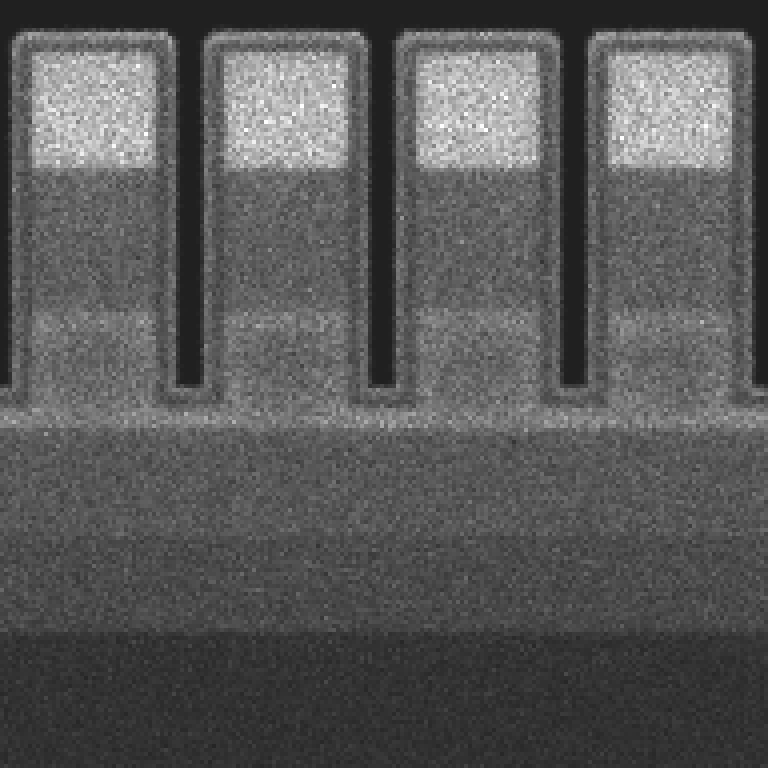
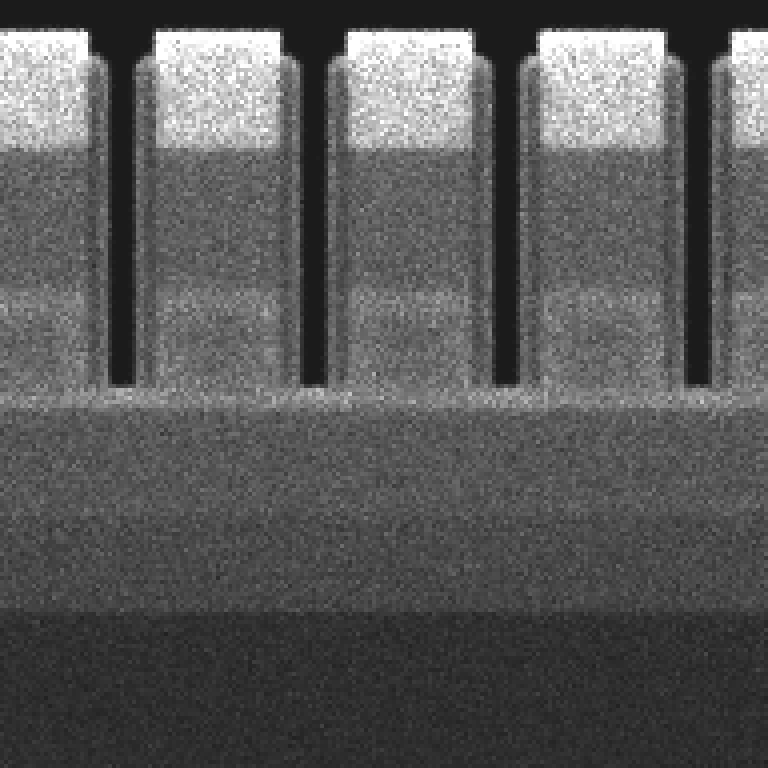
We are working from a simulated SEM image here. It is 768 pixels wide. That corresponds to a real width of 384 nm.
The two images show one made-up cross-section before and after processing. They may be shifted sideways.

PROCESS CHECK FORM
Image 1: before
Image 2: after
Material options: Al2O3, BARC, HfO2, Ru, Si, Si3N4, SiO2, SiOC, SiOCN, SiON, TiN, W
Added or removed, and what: removed, SiOCN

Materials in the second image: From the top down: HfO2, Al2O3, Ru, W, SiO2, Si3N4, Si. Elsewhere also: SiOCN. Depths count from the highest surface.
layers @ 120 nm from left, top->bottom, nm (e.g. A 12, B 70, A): HfO2 58, Al2O3 72, Ru 28, W 30, SiO2 54, Si3N4 48, Si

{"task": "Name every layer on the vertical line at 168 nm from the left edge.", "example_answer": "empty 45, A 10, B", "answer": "empty 12, SiOCN 166, W 10, SiO2 54, Si3N4 48, Si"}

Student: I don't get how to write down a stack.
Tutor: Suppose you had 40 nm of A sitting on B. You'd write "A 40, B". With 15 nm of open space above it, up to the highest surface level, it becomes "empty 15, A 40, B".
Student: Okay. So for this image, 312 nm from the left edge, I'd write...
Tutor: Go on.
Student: HfO2 58, Al2O3 72, Ru 28, W 30, SiO2 54, Si3N4 48, Si